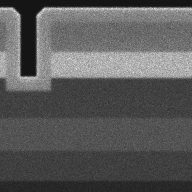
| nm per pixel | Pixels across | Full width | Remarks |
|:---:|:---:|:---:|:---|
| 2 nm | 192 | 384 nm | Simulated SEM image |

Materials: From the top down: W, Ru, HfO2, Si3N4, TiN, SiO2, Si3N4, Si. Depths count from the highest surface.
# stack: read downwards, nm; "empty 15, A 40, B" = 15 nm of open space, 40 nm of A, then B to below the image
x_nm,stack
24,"W 166, Si3N4 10, TiN 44, SiO2 66, Si3N4 60, Si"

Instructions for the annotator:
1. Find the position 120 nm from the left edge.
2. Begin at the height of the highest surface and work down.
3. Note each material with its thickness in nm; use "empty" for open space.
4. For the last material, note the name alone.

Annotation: W 28, Ru 60, HfO2 52, Si3N4 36, TiN 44, SiO2 66, Si3N4 60, Si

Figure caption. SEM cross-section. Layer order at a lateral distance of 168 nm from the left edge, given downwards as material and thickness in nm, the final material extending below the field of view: W 28, Ru 60, HfO2 52, Si3N4 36, TiN 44, SiO2 66, Si3N4 60, Si